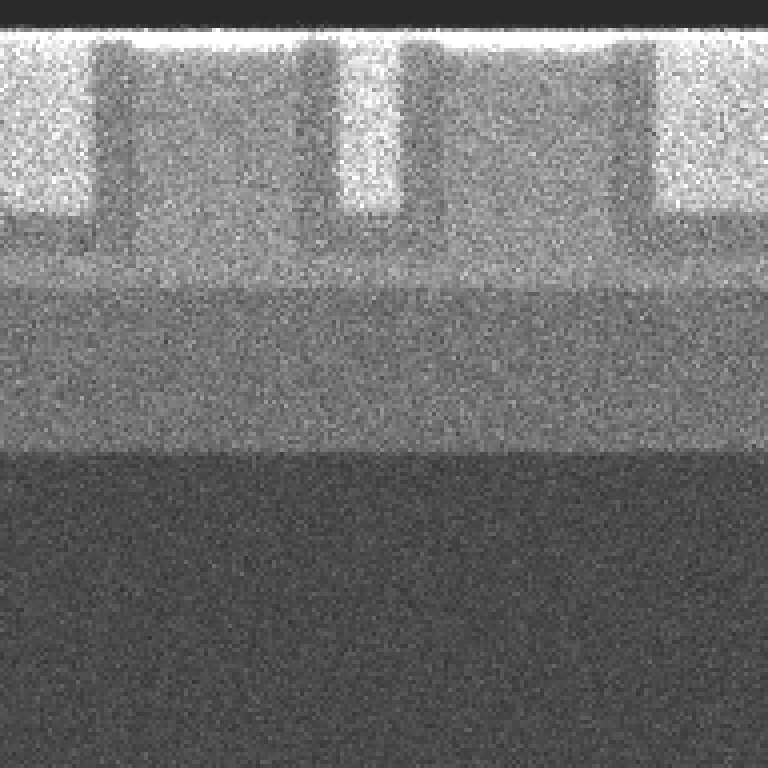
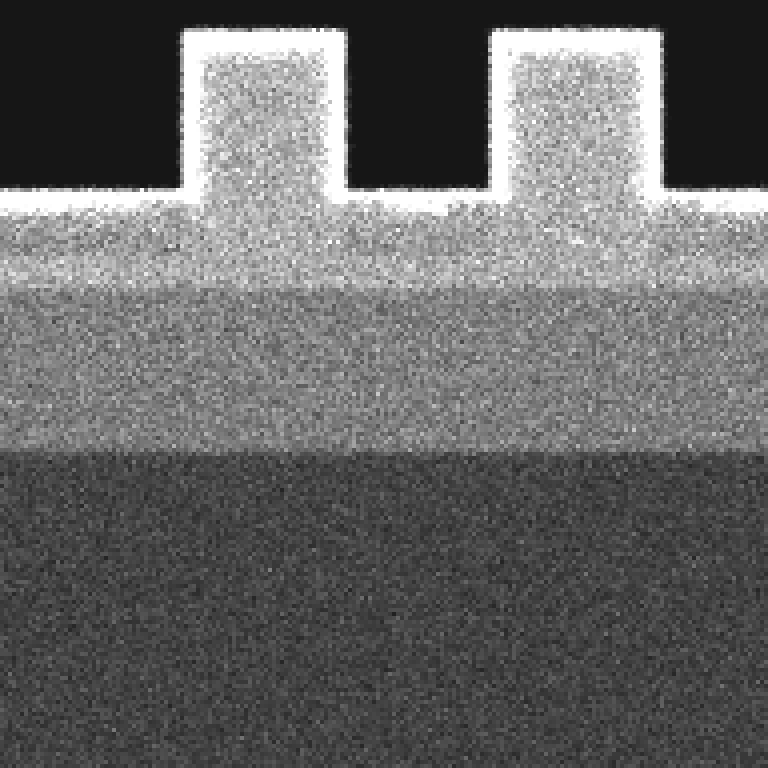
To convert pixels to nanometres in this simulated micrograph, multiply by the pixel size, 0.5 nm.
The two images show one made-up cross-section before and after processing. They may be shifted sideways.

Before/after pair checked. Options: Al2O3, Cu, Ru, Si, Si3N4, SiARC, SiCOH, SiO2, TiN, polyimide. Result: removed Ru and TiN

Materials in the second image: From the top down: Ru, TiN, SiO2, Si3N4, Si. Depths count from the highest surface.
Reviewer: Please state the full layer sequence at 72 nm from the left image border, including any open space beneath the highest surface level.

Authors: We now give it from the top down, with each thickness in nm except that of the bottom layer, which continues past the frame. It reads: empty 80, TiN 32, SiO2 16, Si3N4 82, Si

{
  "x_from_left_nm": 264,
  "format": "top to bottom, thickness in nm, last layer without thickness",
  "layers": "SiO2 128, Si3N4 82, Si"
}